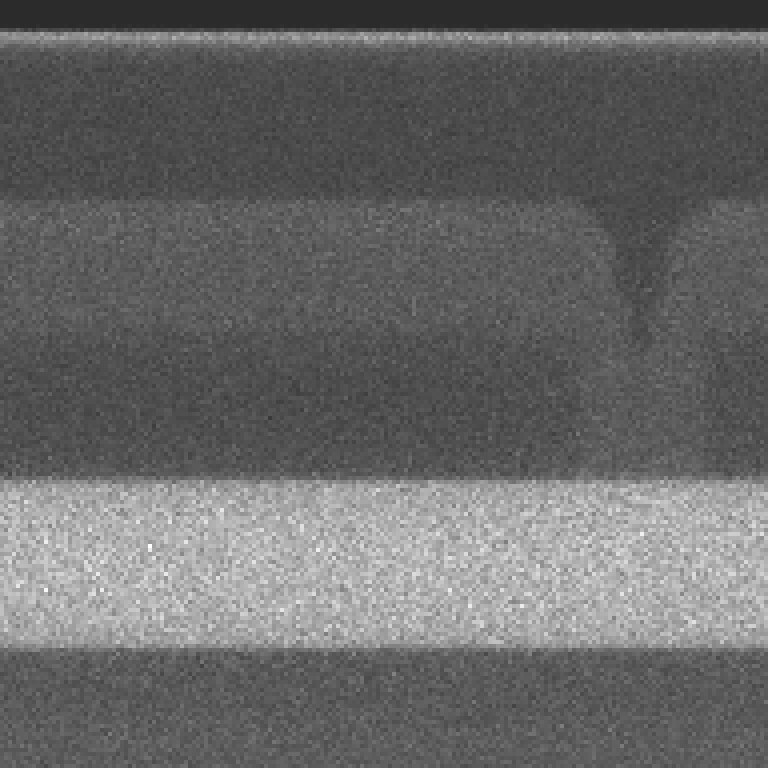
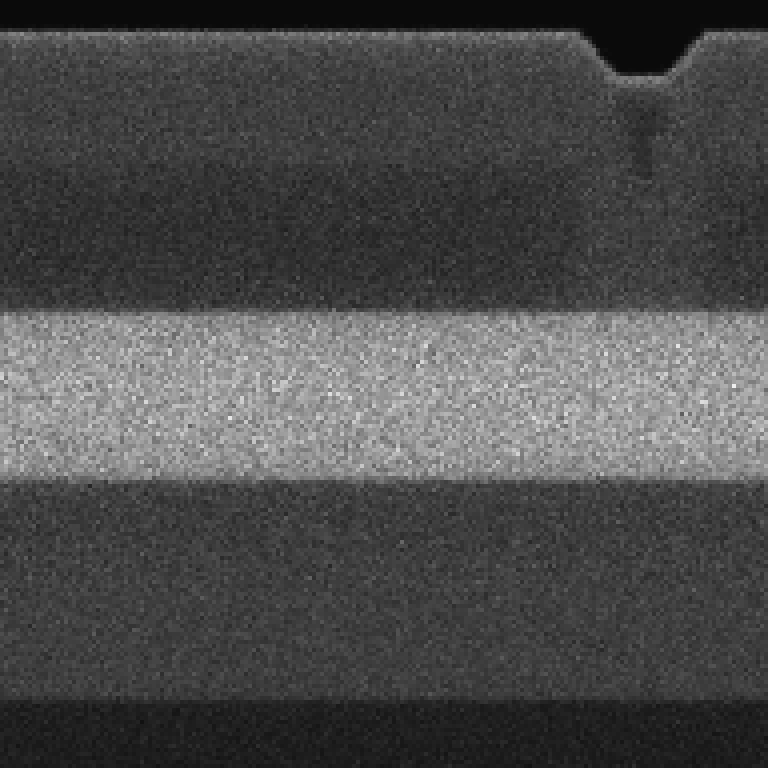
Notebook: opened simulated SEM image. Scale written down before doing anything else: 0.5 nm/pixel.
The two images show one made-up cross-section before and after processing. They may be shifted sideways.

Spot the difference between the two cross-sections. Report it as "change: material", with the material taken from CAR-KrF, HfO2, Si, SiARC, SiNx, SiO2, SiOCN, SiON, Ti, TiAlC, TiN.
removed: SiARC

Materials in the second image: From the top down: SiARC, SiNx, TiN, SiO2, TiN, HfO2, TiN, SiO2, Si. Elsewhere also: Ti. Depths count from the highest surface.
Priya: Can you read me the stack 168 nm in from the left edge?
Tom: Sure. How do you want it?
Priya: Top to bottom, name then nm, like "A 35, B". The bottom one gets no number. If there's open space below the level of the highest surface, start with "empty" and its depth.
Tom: TiN 18, SiO2 36, TiN 12, Ti 74, HfO2 84, TiN 50, SiO2 60, Si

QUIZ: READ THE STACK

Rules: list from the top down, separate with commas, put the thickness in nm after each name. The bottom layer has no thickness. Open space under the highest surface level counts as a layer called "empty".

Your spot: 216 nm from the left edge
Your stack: TiN 18, SiO2 36, TiN 12, Ti 74, HfO2 84, TiN 50, SiO2 60, Si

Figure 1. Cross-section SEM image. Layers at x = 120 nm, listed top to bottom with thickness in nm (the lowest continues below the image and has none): TiN 18, SiO2 36, TiN 12, Ti 74, HfO2 84, TiN 50, SiO2 60, Si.